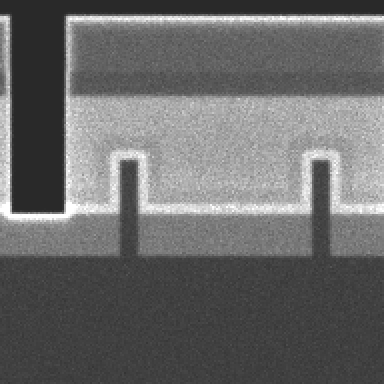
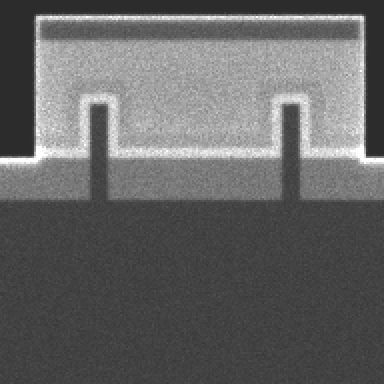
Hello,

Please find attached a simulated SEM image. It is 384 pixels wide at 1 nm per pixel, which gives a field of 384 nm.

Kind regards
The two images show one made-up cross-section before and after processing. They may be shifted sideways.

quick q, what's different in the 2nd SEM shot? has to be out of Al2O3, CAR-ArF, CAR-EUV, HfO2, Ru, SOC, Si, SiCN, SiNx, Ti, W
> SOC removed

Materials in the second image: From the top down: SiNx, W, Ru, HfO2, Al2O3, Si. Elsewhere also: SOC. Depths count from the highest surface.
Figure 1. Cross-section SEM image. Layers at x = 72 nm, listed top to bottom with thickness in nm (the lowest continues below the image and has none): SiNx 24, W 44, Ru 64, HfO2 10, Al2O3 42, Si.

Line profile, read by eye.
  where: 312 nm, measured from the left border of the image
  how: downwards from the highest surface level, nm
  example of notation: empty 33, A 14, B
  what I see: SiNx 24, W 40, Ru 68, HfO2 10, Al2O3 42, Si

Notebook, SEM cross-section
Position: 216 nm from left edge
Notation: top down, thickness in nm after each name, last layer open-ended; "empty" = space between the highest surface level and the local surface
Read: SiNx 24, W 94, Ru 14, HfO2 10, Al2O3 42, Si